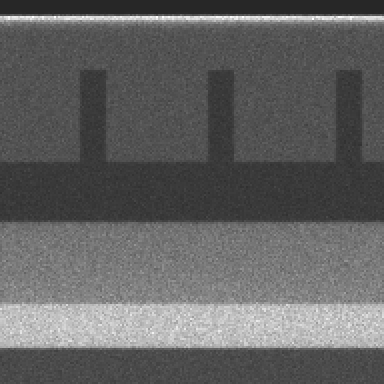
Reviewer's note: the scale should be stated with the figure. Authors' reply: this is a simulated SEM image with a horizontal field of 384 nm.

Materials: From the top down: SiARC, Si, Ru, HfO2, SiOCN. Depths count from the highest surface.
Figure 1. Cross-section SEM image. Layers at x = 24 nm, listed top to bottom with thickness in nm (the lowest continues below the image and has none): SiARC 146, Si 60, Ru 82, HfO2 44, SiOCN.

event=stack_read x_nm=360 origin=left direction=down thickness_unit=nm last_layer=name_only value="SiARC 54, Si 152, Ru 82, HfO2 44, SiOCN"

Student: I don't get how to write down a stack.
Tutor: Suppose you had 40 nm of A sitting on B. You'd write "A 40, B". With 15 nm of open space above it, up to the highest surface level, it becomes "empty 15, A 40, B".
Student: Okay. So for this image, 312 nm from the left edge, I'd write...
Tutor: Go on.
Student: SiARC 146, Si 60, Ru 82, HfO2 44, SiOCN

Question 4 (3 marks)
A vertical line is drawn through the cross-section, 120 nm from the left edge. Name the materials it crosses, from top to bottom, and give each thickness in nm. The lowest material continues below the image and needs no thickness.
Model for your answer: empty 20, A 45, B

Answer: SiARC 146, Si 60, Ru 82, HfO2 44, SiOCN